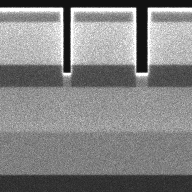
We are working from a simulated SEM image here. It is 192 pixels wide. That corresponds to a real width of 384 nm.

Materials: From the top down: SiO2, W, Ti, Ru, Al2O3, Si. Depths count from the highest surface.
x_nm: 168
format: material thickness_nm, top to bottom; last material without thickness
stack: SiO2 28, W 86, Ti 44, Ru 90, Al2O3 86, Si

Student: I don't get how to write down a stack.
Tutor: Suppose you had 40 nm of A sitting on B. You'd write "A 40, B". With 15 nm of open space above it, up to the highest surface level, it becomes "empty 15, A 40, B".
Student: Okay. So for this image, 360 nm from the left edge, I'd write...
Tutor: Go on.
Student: SiO2 28, W 86, Ti 44, Ru 90, Al2O3 86, Si